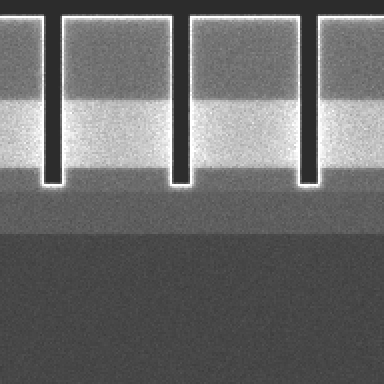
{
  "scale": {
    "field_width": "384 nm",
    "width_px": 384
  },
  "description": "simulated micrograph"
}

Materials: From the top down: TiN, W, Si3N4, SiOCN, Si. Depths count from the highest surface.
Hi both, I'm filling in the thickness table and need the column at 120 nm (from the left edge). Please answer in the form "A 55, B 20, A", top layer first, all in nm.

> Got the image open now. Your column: TiN 84, W 68, Si3N4 24, SiOCN 42, Si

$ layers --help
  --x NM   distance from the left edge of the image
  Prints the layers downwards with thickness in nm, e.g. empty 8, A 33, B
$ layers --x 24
TiN 84, W 68, Si3N4 24, SiOCN 42, Si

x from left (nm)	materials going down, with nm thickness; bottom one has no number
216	TiN 84, W 68, Si3N4 24, SiOCN 42, Si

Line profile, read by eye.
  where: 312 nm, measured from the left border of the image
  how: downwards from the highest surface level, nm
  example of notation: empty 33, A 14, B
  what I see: empty 168, Si3N4 8, SiOCN 42, Si